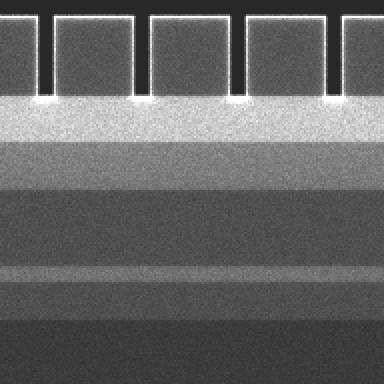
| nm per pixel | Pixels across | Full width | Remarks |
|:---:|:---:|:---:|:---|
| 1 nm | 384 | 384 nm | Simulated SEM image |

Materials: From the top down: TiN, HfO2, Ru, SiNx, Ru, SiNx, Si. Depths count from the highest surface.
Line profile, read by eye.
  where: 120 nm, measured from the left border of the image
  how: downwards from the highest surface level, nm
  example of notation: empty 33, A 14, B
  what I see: TiN 80, HfO2 46, Ru 48, SiNx 76, Ru 16, SiNx 38, Si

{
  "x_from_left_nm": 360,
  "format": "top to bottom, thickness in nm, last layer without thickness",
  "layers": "TiN 80, HfO2 46, Ru 48, SiNx 76, Ru 16, SiNx 38, Si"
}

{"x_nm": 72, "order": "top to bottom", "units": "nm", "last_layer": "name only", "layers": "TiN 80, HfO2 46, Ru 48, SiNx 76, Ru 16, SiNx 38, Si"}